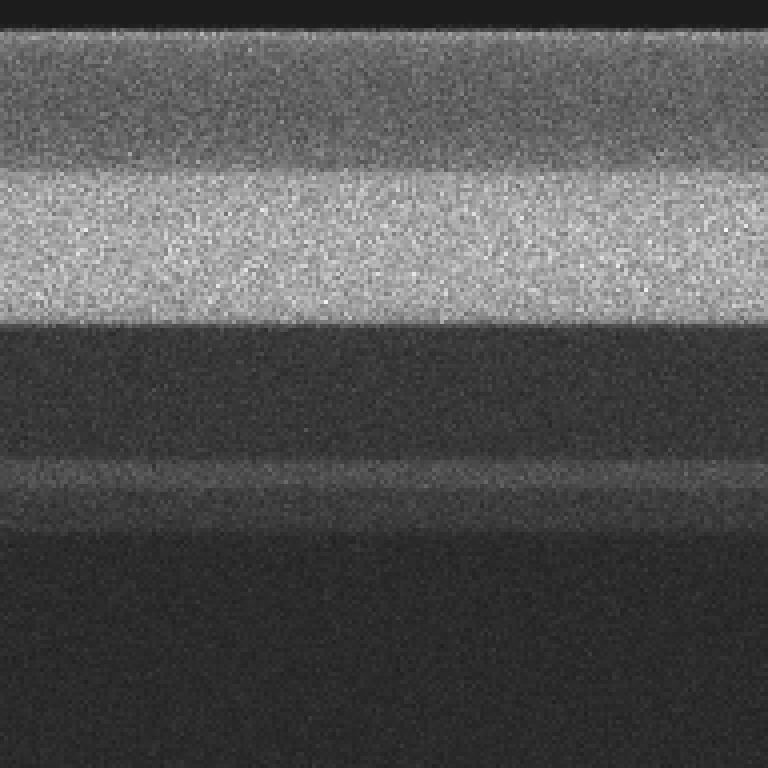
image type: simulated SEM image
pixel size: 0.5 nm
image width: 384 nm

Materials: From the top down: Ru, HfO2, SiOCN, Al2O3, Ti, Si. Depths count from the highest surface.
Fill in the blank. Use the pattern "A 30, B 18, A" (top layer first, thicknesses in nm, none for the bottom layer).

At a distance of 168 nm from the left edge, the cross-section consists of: Ru 70, HfO2 76, SiOCN 68, Al2O3 14, Ti 22, Si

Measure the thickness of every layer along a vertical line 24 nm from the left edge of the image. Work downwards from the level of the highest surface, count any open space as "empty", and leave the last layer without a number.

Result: Ru 70, HfO2 76, SiOCN 68, Al2O3 14, Ti 22, Si